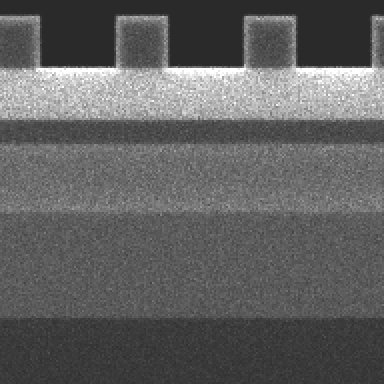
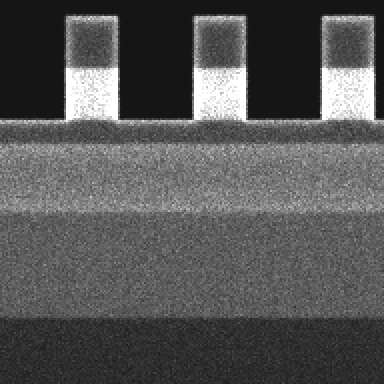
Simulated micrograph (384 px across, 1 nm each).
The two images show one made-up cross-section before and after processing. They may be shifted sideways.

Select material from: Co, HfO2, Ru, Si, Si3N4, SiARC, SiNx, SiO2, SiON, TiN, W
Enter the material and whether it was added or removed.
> HfO2 / removed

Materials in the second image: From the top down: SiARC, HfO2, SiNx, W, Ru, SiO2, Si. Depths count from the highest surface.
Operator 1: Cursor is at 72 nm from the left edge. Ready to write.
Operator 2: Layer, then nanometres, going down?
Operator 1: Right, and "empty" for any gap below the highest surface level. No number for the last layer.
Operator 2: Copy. SiARC 52, HfO2 52, SiNx 24, W 52, Ru 16, SiO2 106, Si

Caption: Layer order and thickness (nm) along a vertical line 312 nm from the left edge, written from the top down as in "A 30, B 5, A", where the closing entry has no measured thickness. empty 104, SiNx 24, W 52, Ru 16, SiO2 106, Si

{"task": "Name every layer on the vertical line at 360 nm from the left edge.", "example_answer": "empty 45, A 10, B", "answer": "SiARC 52, HfO2 52, SiNx 24, W 52, Ru 16, SiO2 106, Si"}